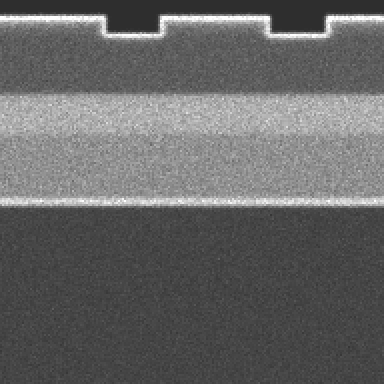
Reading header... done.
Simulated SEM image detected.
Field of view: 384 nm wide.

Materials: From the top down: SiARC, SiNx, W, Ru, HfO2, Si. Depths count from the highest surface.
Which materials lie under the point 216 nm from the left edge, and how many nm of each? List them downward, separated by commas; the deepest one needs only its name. SiARC 18, SiNx 60, W 40, Ru 64, HfO2 8, Si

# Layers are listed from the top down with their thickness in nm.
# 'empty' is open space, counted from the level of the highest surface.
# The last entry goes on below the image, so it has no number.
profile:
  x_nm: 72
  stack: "SiARC 18, SiNx 60, W 40, Ru 64, HfO2 8, Si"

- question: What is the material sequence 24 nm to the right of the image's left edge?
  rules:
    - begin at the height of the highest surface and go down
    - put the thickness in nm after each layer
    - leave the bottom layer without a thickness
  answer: SiARC 18, SiNx 60, W 40, Ru 64, HfO2 8, Si